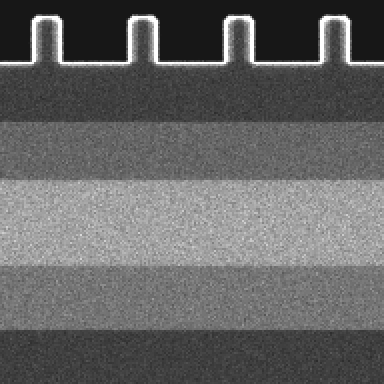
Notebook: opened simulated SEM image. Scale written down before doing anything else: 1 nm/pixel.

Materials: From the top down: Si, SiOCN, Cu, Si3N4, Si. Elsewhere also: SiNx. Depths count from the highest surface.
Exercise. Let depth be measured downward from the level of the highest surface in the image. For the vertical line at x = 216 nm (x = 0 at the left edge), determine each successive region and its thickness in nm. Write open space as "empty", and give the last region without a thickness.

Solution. empty 46, Si 60, SiOCN 58, Cu 86, Si3N4 64, Si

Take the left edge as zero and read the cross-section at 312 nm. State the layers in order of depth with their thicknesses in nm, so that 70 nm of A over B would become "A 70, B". empty 46, Si 60, SiOCN 58, Cu 86, Si3N4 64, Si